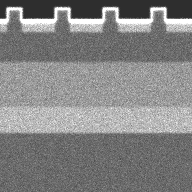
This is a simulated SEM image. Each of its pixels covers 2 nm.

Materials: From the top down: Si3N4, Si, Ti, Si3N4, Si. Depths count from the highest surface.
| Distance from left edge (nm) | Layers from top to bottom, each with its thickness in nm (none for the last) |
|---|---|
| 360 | empty 24, Si3N4 24, Si 60, Ti 90, Si3N4 52, Si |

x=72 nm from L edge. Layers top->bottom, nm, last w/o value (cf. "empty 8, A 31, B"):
empty 24, Si3N4 24, Si 60, Ti 90, Si3N4 52, Si